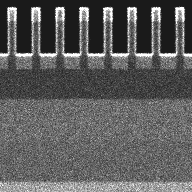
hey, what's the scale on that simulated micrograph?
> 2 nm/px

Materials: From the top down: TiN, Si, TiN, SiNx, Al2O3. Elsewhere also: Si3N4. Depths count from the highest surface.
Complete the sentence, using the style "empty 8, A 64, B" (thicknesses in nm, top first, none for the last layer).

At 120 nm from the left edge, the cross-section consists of TiN 26, Si 156, TiN 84, SiNx 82, Al2O3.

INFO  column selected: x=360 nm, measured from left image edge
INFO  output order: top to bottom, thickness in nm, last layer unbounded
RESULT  TiN 26, Si 156, TiN 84, SiNx 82, Al2O3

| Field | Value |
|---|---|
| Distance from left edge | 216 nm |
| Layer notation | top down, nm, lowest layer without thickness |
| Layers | TiN 26, Si 156, TiN 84, SiNx 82, Al2O3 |